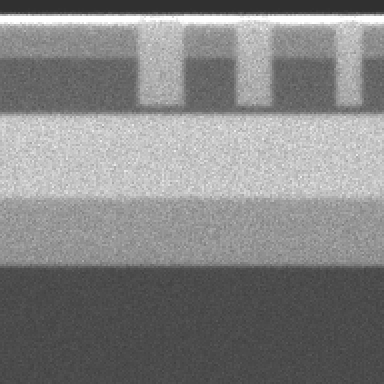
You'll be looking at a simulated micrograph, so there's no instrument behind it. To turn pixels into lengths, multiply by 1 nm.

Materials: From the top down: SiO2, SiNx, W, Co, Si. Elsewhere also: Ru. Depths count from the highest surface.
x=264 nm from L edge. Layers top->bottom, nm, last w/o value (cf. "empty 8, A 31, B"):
Ru 90, SiNx 8, W 84, Co 68, Si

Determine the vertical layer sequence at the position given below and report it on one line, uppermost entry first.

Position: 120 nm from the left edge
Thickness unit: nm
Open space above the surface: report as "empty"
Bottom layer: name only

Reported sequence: SiO2 42, SiNx 56, W 84, Co 68, Si